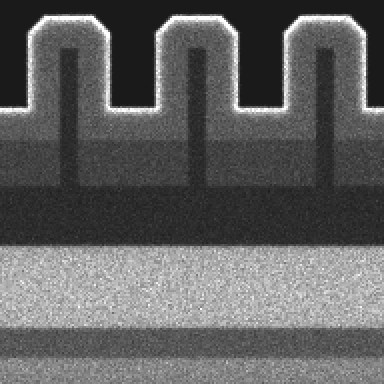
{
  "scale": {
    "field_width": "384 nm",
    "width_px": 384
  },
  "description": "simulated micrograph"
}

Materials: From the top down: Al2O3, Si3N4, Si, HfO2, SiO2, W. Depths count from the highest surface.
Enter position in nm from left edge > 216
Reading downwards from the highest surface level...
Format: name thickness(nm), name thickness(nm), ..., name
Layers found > Al2O3 124, Si3N4 46, Si 60, HfO2 82, SiO2 30, W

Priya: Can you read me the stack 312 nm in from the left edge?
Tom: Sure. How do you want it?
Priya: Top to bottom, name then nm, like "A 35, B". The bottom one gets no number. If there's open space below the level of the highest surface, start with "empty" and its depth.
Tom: Al2O3 124, Si3N4 46, Si 60, HfO2 82, SiO2 30, W